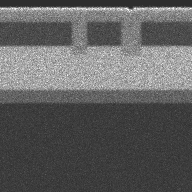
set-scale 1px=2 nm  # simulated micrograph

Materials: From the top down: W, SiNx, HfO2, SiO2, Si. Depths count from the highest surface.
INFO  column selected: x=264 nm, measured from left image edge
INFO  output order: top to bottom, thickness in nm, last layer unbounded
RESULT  empty 4, W 90, HfO2 70, SiO2 26, Si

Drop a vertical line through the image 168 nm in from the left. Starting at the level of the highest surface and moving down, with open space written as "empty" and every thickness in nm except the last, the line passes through W 94, HfO2 70, SiO2 26, Si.